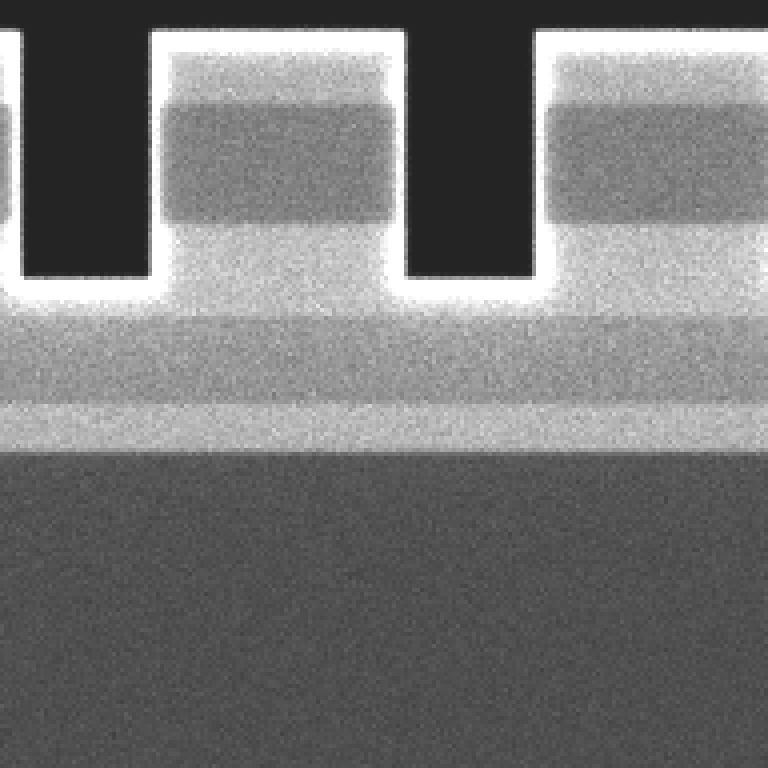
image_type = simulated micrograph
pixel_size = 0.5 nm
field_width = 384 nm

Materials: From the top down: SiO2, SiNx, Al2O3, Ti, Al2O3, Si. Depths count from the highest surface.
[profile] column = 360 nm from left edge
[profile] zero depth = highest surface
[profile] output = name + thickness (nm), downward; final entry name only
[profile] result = SiO2 36, SiNx 60, Al2O3 46, Ti 44, Al2O3 24, Si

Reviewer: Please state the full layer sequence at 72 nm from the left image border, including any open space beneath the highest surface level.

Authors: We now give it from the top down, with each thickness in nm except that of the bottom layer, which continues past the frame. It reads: empty 124, Al2O3 18, Ti 44, Al2O3 24, Si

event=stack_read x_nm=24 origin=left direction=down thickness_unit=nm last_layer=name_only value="empty 124, Al2O3 18, Ti 44, Al2O3 24, Si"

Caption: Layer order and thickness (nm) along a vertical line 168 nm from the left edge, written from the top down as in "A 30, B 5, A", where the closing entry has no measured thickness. SiO2 36, SiNx 60, Al2O3 46, Ti 44, Al2O3 24, Si